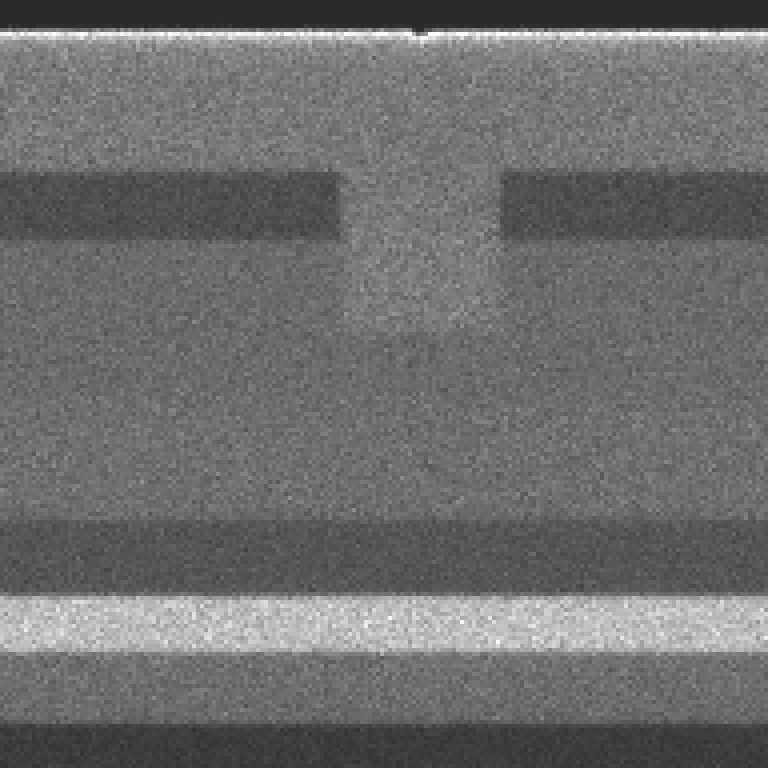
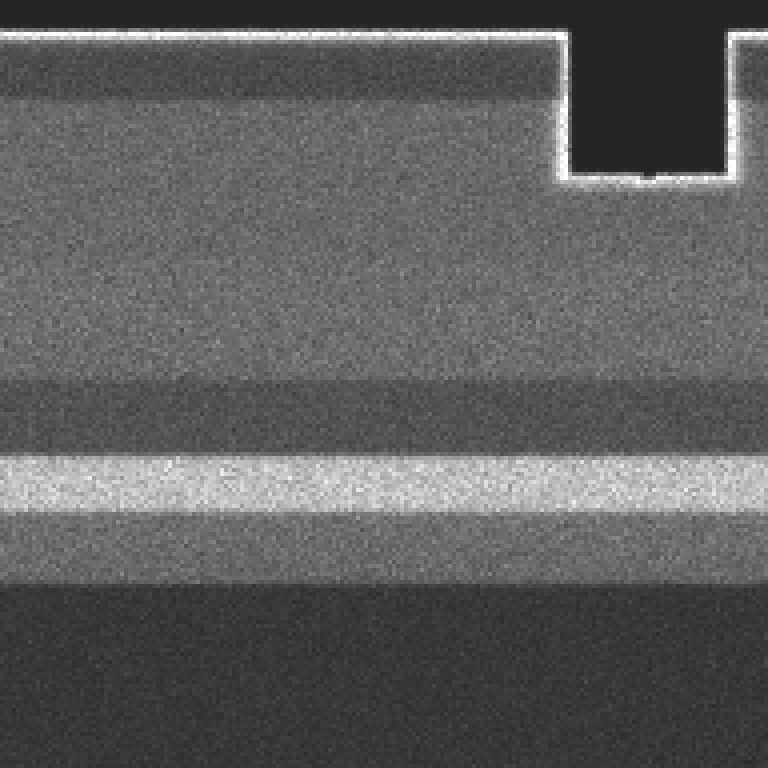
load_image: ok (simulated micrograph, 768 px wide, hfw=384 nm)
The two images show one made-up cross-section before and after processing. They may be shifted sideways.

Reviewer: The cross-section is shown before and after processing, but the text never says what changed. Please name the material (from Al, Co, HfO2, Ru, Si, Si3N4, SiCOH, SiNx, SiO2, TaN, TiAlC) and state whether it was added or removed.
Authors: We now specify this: Ru, removed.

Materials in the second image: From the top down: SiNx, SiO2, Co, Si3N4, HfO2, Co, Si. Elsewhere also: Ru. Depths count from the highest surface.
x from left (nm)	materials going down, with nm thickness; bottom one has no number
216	SiNx 34, SiO2 80, Co 60, Si3N4 38, HfO2 28, Co 36, Si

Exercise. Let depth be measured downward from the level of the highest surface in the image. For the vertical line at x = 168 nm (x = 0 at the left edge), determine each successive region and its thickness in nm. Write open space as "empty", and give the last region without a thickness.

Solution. SiNx 34, SiO2 80, Co 60, Si3N4 38, HfO2 28, Co 36, Si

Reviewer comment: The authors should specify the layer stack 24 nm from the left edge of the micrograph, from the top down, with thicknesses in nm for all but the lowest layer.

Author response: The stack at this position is SiNx 34, SiO2 80, Co 60, Si3N4 38, HfO2 28, Co 36, Si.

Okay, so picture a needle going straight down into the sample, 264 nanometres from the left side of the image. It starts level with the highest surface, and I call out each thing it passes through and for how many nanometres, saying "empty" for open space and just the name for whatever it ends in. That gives SiNx 34, SiO2 80, Co 60, Si3N4 38, HfO2 28, Co 36, Si